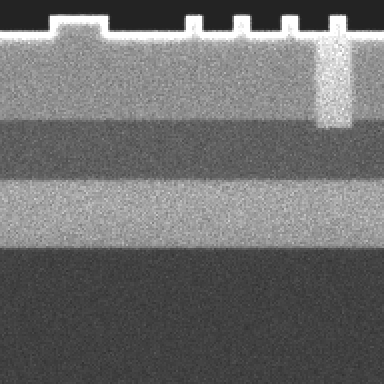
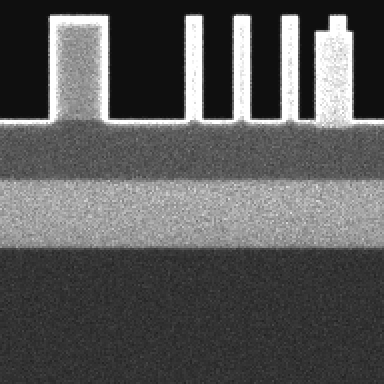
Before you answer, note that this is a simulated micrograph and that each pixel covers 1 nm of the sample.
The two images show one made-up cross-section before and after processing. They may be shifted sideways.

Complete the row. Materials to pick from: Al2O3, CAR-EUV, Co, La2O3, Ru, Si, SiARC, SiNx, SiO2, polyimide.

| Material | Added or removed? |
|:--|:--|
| Al2O3 | removed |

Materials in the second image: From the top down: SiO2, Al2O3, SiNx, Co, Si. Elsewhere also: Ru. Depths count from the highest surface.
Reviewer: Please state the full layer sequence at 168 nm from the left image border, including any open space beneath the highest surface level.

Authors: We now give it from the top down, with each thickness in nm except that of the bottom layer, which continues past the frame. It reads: empty 104, SiNx 60, Co 68, Si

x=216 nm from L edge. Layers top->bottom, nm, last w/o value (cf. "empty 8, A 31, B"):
empty 104, SiNx 60, Co 68, Si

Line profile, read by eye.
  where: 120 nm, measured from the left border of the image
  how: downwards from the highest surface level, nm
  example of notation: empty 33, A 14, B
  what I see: empty 104, SiNx 60, Co 68, Si